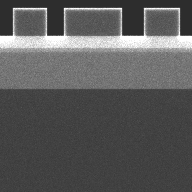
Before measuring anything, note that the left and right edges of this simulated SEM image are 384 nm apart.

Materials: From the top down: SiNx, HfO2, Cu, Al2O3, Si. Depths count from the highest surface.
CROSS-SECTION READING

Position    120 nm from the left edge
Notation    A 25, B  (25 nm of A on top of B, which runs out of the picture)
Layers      empty 56, HfO2 24, Cu 8, Al2O3 74, Si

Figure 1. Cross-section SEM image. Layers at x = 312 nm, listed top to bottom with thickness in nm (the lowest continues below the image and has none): SiNx 56, HfO2 24, Cu 8, Al2O3 74, Si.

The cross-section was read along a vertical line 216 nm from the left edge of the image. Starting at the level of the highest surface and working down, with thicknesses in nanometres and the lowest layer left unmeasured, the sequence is SiNx 56, HfO2 24, Cu 8, Al2O3 74, Si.